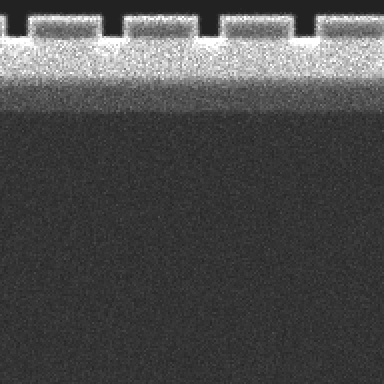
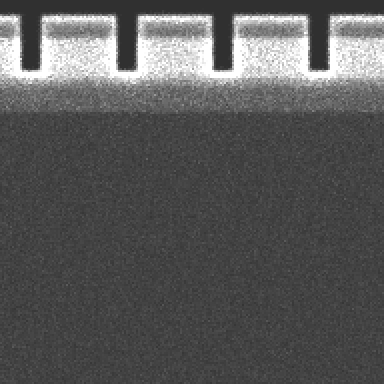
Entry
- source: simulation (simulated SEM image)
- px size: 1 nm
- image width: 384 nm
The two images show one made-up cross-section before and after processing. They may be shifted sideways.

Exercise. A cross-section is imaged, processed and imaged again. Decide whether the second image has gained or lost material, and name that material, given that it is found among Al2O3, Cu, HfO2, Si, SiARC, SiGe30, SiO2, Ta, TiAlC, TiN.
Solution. removed: HfO2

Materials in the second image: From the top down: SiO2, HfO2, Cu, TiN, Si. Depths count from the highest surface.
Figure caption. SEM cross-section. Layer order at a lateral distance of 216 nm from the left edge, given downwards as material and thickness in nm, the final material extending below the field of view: empty 56, HfO2 6, Cu 8, TiN 26, Si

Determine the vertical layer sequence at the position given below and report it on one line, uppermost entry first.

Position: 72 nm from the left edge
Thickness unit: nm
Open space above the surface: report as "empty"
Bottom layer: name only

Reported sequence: SiO2 22, HfO2 40, Cu 8, TiN 26, Si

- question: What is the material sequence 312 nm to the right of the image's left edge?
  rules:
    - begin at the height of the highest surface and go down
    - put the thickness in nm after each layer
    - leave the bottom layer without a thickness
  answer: empty 56, HfO2 6, Cu 8, TiN 26, Si